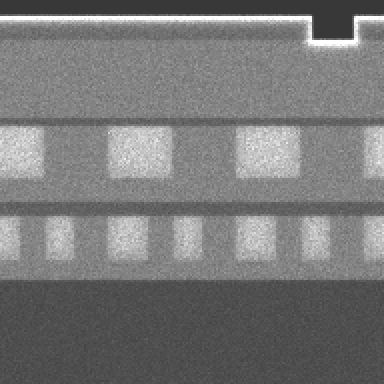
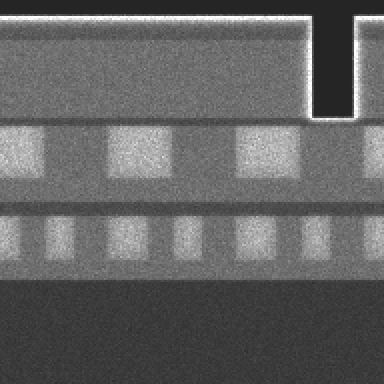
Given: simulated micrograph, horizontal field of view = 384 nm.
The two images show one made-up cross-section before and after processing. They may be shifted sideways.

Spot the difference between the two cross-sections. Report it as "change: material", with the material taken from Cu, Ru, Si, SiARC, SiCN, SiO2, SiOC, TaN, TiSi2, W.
removed: SiO2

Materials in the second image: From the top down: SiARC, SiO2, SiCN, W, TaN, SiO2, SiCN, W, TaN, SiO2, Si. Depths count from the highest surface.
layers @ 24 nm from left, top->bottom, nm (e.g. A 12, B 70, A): SiARC 24, SiO2 78, SiCN 8, W 42, TaN 10, SiO2 24, SiCN 14, SiO2 64, Si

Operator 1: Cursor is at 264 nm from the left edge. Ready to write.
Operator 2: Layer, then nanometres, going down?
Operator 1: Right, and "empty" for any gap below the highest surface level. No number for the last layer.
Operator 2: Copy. SiARC 24, SiO2 78, SiCN 8, W 42, TaN 10, SiO2 24, SiCN 14, W 34, TaN 10, SiO2 20, Si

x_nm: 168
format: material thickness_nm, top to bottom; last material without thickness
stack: SiARC 24, SiO2 78, SiCN 8, TaN 52, SiO2 24, SiCN 14, SiO2 64, Si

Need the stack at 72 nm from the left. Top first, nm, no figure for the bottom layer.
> SiARC 24, SiO2 78, SiCN 8, SiO2 76, SiCN 14, TaN 44, SiO2 20, Si